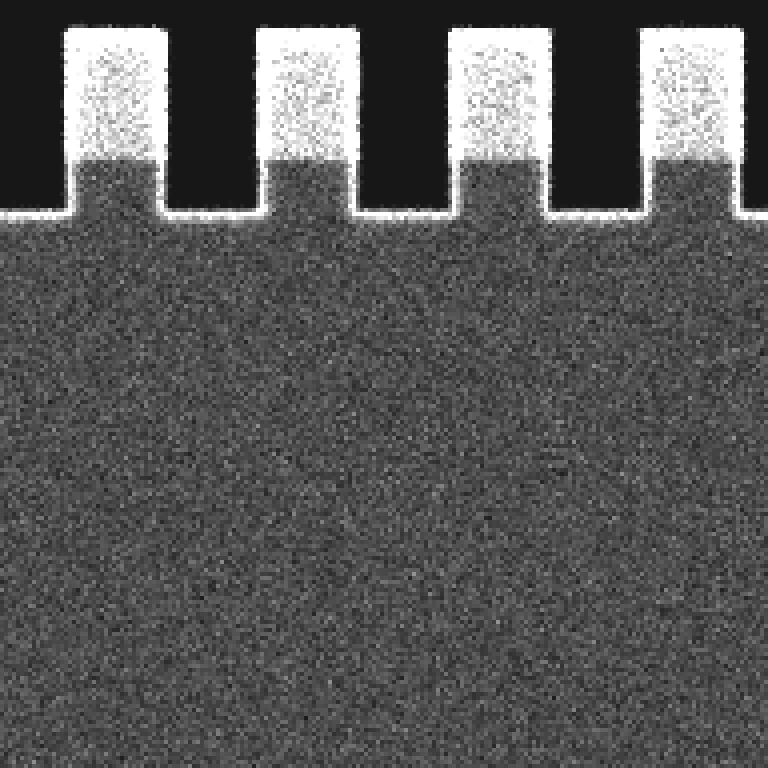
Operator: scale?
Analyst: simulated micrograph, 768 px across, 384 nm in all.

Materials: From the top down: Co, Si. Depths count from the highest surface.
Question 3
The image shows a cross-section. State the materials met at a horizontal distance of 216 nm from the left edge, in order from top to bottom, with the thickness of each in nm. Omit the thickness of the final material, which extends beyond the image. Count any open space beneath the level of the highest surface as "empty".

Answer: empty 90, Si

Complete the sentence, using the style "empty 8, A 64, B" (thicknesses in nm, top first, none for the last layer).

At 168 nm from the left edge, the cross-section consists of Co 64, Si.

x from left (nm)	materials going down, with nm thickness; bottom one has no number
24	empty 90, Si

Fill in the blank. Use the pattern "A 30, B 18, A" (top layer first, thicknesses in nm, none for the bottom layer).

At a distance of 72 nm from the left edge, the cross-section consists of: Co 64, Si